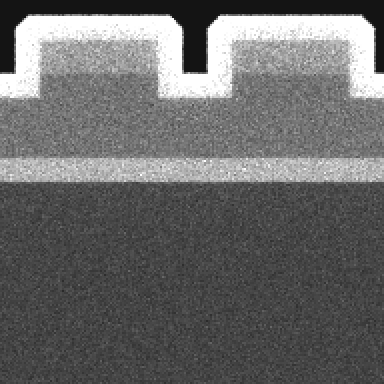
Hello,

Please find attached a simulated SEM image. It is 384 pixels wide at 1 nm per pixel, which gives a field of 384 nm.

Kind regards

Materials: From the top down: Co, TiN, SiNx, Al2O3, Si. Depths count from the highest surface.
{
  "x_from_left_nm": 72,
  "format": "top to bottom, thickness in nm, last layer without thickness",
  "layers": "Co 24, TiN 34, SiNx 84, Al2O3 24, Si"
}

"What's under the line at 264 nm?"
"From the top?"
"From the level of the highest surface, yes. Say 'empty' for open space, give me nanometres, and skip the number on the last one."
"Co 24, TiN 34, SiNx 84, Al2O3 24, Si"